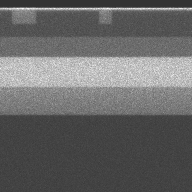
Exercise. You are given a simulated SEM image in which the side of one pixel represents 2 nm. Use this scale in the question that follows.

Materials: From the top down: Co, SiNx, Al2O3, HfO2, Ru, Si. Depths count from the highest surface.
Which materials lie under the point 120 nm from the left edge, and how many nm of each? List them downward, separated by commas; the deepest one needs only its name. SiNx 58, Al2O3 40, HfO2 60, Ru 56, Si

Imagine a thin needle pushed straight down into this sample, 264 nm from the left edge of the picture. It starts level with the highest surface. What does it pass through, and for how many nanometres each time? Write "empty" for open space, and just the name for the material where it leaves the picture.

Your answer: SiNx 58, Al2O3 40, HfO2 60, Ru 56, Si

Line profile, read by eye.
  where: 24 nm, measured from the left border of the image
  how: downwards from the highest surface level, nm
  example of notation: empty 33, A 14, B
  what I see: Co 32, SiNx 26, Al2O3 40, HfO2 60, Ru 56, Si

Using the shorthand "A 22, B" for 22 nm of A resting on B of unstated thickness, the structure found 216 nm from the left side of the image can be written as Co 32, SiNx 26, Al2O3 40, HfO2 60, Ru 56, Si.